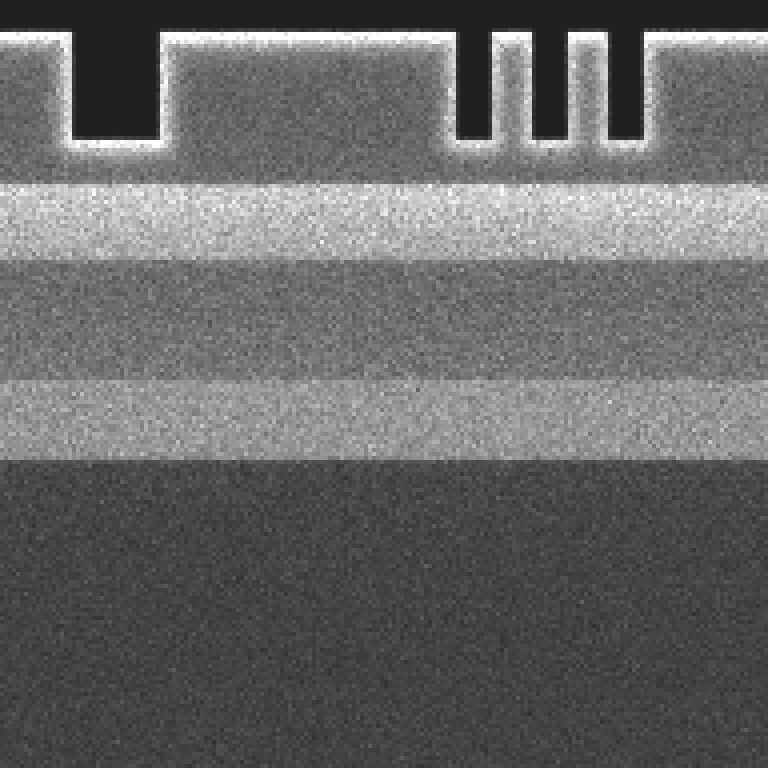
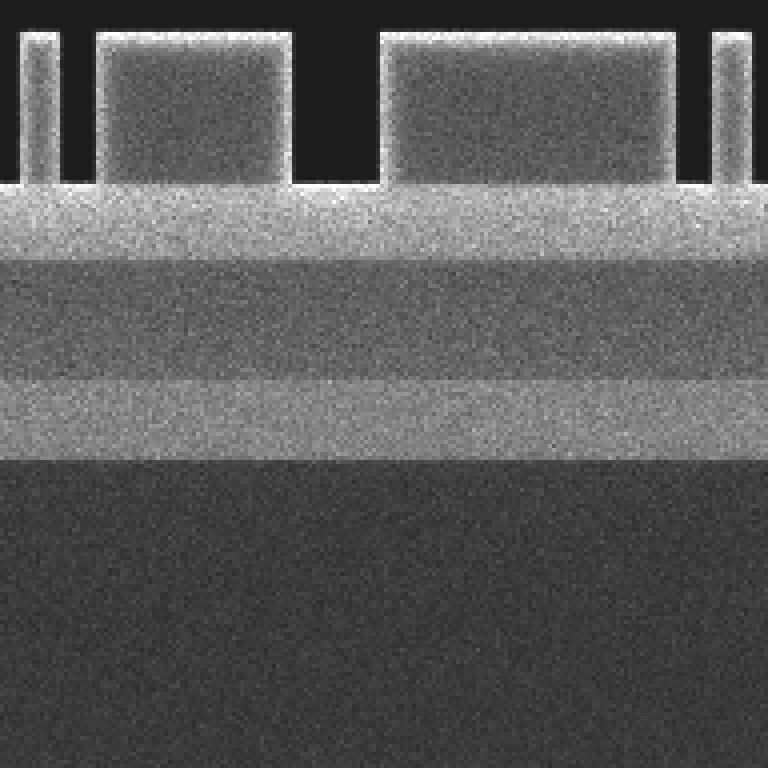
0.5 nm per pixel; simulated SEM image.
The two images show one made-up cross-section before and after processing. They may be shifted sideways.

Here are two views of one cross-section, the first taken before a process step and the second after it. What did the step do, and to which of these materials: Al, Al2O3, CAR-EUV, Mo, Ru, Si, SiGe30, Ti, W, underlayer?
It removed underlayer.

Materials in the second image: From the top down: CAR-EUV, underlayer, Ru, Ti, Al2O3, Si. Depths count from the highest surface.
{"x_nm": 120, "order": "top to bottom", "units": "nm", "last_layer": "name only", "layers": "CAR-EUV 54, underlayer 22, Ru 38, Ti 60, Al2O3 40, Si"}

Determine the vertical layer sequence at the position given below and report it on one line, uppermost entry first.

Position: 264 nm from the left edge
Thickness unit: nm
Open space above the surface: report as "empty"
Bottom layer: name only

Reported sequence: CAR-EUV 54, underlayer 22, Ru 38, Ti 60, Al2O3 40, Si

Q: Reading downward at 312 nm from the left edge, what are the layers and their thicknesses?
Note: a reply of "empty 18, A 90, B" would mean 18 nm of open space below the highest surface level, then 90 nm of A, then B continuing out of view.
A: CAR-EUV 54, underlayer 22, Ru 38, Ti 60, Al2O3 40, Si